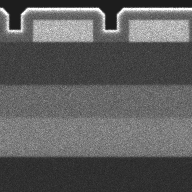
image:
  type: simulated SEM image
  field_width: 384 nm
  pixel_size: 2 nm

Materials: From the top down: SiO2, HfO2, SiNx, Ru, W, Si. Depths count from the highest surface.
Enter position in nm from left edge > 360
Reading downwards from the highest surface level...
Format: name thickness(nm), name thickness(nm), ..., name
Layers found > SiO2 24, HfO2 44, SiNx 86, Ru 66, W 78, Si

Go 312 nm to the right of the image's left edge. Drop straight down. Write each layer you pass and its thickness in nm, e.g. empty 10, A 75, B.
SiO2 24, HfO2 44, SiNx 86, Ru 66, W 78, Si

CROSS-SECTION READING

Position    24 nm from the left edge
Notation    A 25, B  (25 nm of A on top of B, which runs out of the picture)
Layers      empty 44, SiO2 24, SiNx 86, Ru 66, W 78, Si